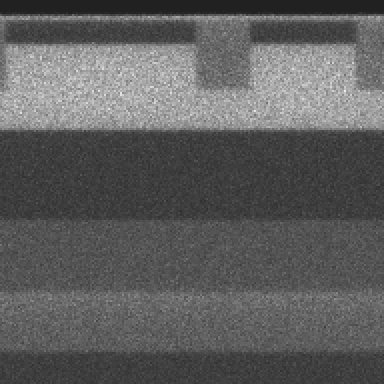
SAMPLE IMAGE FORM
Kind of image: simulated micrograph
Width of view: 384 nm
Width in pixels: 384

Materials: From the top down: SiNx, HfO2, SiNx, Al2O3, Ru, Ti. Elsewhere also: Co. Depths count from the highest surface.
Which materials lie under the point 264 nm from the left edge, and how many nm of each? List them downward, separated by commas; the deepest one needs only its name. SiNx 28, HfO2 86, SiNx 90, Al2O3 72, Ru 60, Ti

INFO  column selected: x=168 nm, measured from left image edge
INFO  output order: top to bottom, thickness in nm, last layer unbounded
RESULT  SiNx 28, HfO2 86, SiNx 90, Al2O3 72, Ru 60, Ti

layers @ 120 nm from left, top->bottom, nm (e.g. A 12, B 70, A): SiNx 28, HfO2 86, SiNx 90, Al2O3 72, Ru 60, Ti